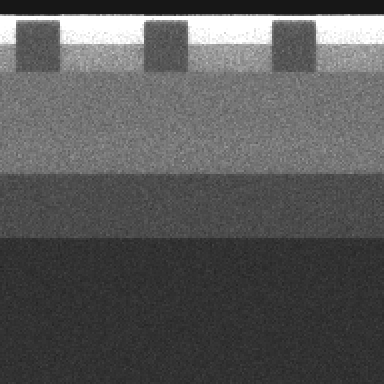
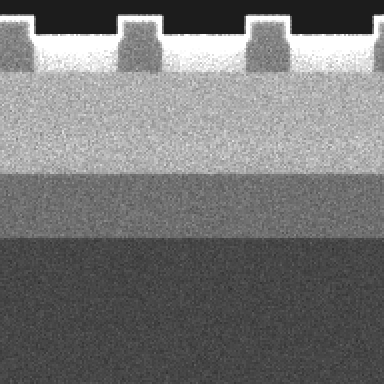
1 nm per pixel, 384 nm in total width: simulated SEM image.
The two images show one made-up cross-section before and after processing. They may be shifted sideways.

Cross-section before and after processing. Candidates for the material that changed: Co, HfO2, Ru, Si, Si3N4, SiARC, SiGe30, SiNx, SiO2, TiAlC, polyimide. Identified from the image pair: HfO2 (removed).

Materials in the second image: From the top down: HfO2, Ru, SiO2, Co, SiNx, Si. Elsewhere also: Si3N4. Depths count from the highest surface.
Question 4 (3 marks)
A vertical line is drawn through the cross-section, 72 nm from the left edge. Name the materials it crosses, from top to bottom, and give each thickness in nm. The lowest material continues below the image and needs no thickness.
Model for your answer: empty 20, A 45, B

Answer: empty 20, HfO2 8, Ru 28, SiO2 60, Co 42, SiNx 64, Si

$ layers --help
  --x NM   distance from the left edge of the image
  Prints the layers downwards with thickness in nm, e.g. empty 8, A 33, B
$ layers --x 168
empty 20, HfO2 8, Ru 28, SiO2 60, Co 42, SiNx 64, Si